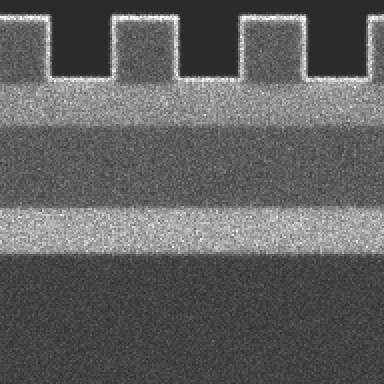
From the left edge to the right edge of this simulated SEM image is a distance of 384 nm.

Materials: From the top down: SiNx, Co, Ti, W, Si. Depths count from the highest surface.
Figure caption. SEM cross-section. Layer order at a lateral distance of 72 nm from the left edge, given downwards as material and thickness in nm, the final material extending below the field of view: empty 62, SiNx 6, Co 42, Ti 82, W 46, Si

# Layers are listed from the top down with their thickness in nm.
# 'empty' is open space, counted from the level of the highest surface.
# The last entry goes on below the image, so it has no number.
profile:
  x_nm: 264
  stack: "SiNx 68, Co 42, Ti 82, W 46, Si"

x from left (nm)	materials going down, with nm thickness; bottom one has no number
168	SiNx 68, Co 42, Ti 82, W 46, Si